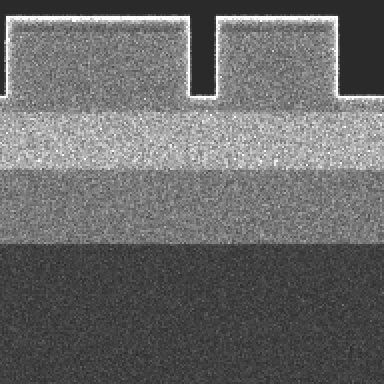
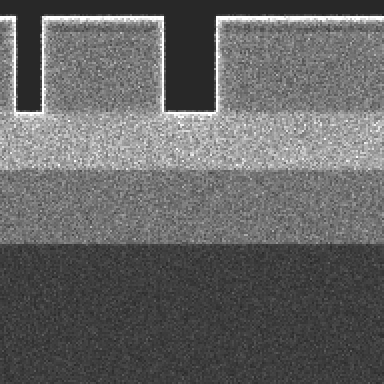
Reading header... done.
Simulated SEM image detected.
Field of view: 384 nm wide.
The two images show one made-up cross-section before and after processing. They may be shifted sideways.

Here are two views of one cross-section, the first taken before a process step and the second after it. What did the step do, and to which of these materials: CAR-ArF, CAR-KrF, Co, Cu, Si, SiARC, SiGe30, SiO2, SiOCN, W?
It removed Co.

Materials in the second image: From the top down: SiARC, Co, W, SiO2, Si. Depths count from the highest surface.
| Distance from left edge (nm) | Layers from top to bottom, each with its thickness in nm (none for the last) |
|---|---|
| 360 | SiARC 16, Co 80, W 58, SiO2 74, Si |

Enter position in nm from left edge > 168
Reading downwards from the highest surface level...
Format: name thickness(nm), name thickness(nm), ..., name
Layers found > empty 96, W 58, SiO2 74, Si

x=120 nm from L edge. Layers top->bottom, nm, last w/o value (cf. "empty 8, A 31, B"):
SiARC 16, Co 80, W 58, SiO2 74, Si